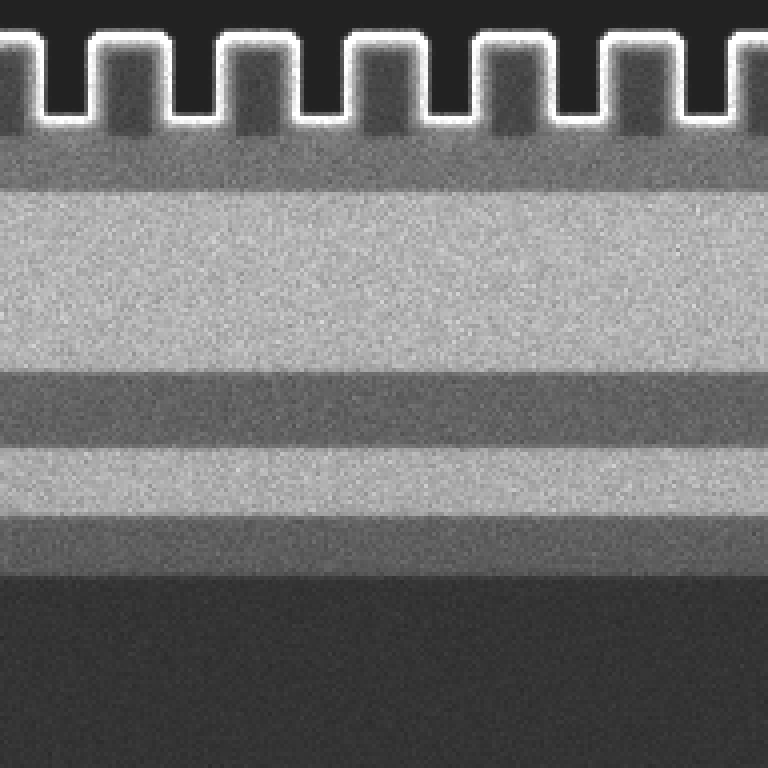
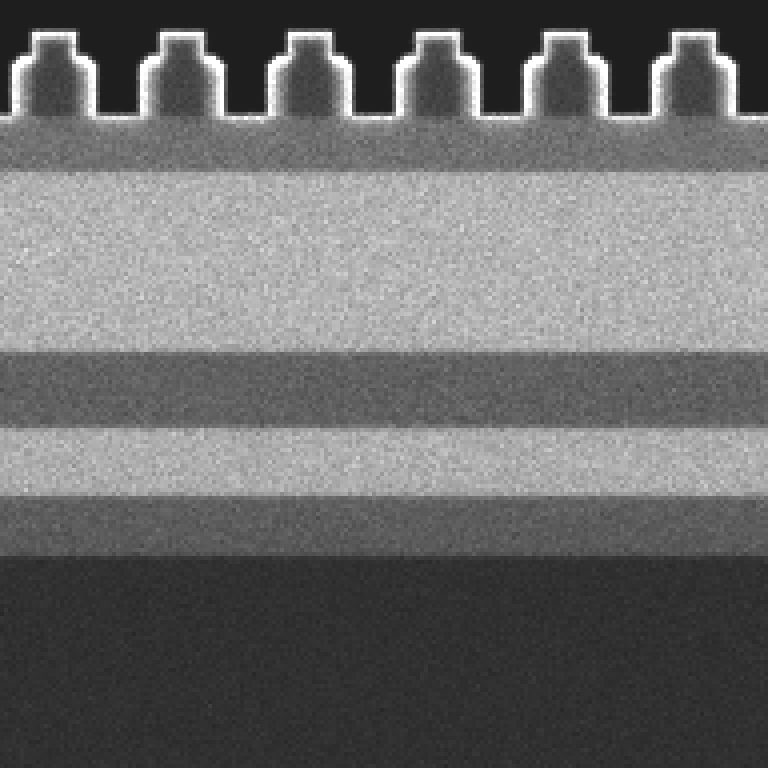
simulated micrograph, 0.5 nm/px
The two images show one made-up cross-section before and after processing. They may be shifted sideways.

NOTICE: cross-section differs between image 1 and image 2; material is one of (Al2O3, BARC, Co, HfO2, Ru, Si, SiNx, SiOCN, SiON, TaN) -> removed: Al2O3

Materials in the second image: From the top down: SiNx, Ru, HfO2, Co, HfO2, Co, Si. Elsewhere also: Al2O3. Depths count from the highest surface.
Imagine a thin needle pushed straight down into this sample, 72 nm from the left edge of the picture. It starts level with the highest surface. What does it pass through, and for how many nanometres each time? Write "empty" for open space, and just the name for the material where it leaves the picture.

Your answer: empty 14, Al2O3 28, Ru 28, HfO2 90, Co 38, HfO2 34, Co 30, Si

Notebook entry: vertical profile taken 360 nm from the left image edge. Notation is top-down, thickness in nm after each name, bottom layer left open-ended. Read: empty 12, Al2O3 30, Ru 28, HfO2 90, Co 38, HfO2 34, Co 30, Si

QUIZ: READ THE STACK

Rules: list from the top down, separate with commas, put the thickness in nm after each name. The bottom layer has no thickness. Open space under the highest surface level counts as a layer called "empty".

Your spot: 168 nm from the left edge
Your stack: empty 12, Al2O3 30, Ru 28, HfO2 90, Co 38, HfO2 34, Co 30, Si